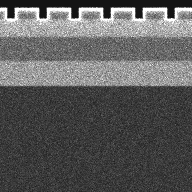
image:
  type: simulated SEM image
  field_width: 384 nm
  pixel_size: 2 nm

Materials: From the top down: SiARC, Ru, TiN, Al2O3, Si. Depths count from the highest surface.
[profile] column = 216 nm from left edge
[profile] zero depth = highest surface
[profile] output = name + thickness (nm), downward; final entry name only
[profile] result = empty 22, Ru 36, TiN 48, Al2O3 50, Si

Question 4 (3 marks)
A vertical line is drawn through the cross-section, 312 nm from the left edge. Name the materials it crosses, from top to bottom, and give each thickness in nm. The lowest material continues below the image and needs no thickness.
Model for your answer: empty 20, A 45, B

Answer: SiARC 22, Ru 36, TiN 48, Al2O3 50, Si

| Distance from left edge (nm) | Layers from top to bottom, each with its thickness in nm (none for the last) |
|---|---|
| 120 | SiARC 22, Ru 36, TiN 48, Al2O3 50, Si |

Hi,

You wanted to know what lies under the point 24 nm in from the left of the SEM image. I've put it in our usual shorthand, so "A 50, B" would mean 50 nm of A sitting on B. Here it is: empty 22, Ru 36, TiN 48, Al2O3 50, Si